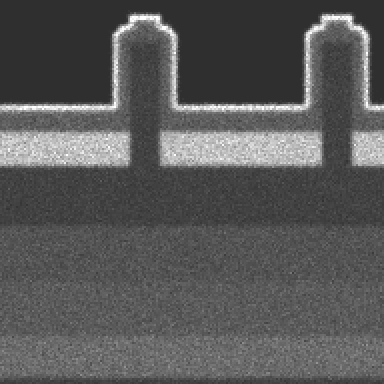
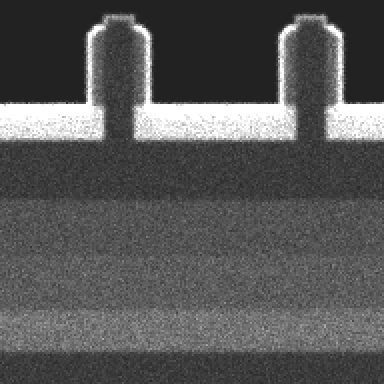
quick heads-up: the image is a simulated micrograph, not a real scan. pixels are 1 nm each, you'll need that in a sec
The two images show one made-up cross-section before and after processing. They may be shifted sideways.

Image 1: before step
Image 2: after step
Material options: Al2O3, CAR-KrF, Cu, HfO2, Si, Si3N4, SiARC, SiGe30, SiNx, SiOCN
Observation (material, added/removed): Si3N4, removed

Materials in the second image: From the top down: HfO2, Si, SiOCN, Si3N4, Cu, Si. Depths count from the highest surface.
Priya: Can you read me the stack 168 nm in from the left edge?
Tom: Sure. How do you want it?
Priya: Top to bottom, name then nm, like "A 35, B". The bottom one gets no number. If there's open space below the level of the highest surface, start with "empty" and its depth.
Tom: empty 90, HfO2 34, Si 60, SiOCN 56, Si3N4 54, Cu 42, Si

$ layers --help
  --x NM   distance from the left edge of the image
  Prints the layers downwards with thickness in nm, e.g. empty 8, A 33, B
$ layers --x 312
Si 184, SiOCN 56, Si3N4 54, Cu 42, Si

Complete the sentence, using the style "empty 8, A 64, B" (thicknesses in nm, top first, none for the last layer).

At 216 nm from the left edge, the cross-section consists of empty 90, HfO2 34, Si 60, SiOCN 56, Si3N4 54, Cu 42, Si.